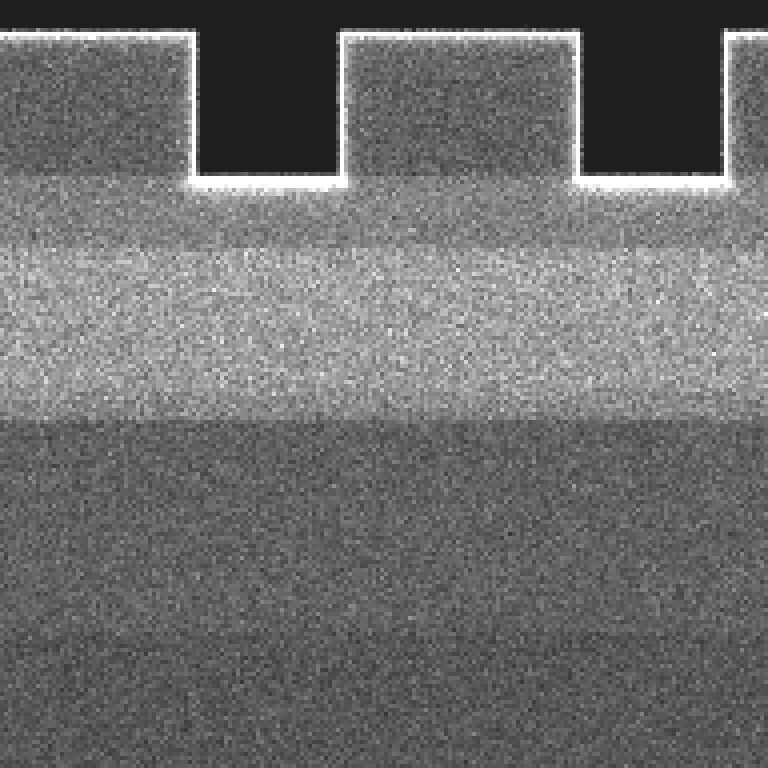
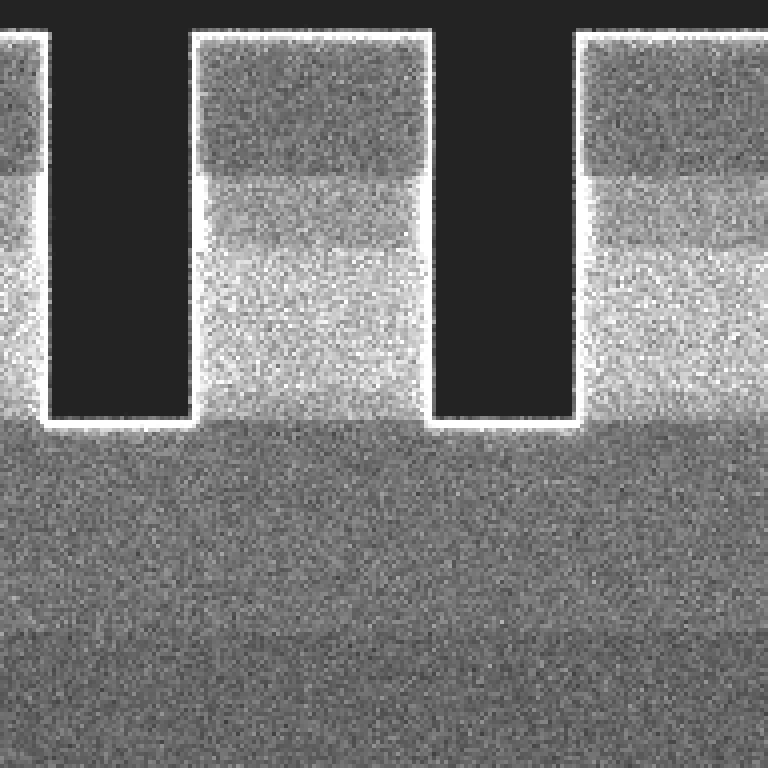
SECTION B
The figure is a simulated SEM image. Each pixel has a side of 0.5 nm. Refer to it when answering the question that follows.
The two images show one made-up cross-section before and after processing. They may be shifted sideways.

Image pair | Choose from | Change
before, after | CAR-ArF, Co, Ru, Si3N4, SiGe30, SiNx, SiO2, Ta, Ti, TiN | Co and Ru and SiO2 (removed)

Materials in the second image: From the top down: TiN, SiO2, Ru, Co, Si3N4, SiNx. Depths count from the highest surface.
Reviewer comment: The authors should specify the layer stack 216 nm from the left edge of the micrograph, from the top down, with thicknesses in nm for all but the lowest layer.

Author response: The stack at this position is empty 194, Si3N4 106, SiNx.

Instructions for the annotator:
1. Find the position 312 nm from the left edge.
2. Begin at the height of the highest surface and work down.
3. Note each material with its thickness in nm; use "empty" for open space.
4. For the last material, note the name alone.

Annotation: TiN 72, SiO2 36, Ru 72, Co 14, Si3N4 106, SiNx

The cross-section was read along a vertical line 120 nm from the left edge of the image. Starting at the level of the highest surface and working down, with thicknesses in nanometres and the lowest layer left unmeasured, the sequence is TiN 72, SiO2 36, Ru 72, Co 14, Si3N4 106, SiNx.